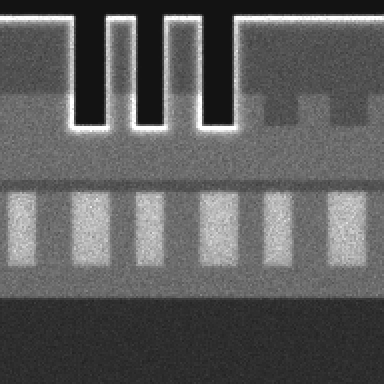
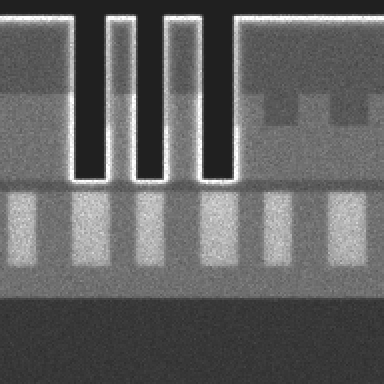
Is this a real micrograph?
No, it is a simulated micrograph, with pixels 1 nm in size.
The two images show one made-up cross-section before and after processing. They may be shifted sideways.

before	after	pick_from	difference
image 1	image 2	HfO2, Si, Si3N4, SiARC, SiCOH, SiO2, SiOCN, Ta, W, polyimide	SiO2 removed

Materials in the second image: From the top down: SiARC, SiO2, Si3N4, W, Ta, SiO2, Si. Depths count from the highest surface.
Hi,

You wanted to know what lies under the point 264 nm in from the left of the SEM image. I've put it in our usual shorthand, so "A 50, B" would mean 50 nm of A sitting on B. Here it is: SiARC 110, SiO2 54, Si3N4 12, Ta 74, SiO2 32, Si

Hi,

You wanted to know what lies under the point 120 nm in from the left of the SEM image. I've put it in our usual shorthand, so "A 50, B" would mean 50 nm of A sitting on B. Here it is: SiARC 78, SiO2 86, Si3N4 12, SiO2 106, Si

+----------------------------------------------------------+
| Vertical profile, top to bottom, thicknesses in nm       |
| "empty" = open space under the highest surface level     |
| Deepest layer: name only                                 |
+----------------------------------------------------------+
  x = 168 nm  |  SiARC 110, SiO2 54, Si3N4 12, SiO2 106, Si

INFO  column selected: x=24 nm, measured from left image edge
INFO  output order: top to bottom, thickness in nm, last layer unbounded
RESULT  SiARC 78, SiO2 86, Si3N4 12, W 68, Ta 6, SiO2 32, Si